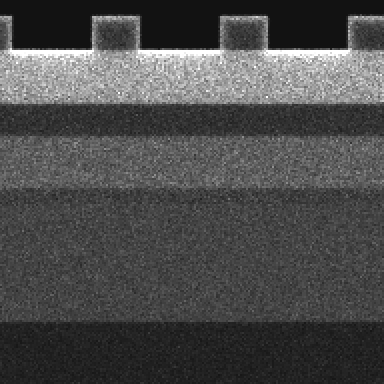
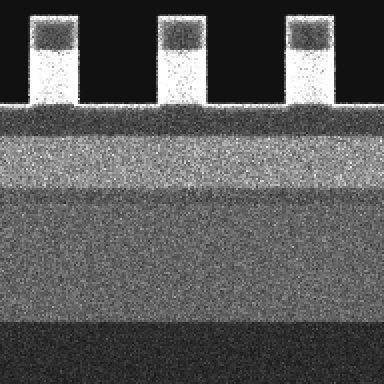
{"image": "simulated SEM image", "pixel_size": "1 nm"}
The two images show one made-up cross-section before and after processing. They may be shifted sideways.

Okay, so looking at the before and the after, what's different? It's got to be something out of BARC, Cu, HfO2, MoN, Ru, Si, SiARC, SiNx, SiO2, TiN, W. HfO2, removed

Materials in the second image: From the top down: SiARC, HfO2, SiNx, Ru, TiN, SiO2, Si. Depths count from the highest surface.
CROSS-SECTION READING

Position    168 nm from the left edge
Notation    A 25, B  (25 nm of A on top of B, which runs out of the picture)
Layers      SiARC 34, HfO2 54, SiNx 32, Ru 52, TiN 16, SiO2 118, Si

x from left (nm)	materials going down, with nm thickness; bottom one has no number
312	SiARC 34, HfO2 54, SiNx 32, Ru 52, TiN 16, SiO2 118, Si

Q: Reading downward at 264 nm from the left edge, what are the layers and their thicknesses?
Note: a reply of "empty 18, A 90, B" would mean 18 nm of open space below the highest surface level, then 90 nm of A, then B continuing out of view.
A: empty 88, SiNx 32, Ru 52, TiN 16, SiO2 118, Si